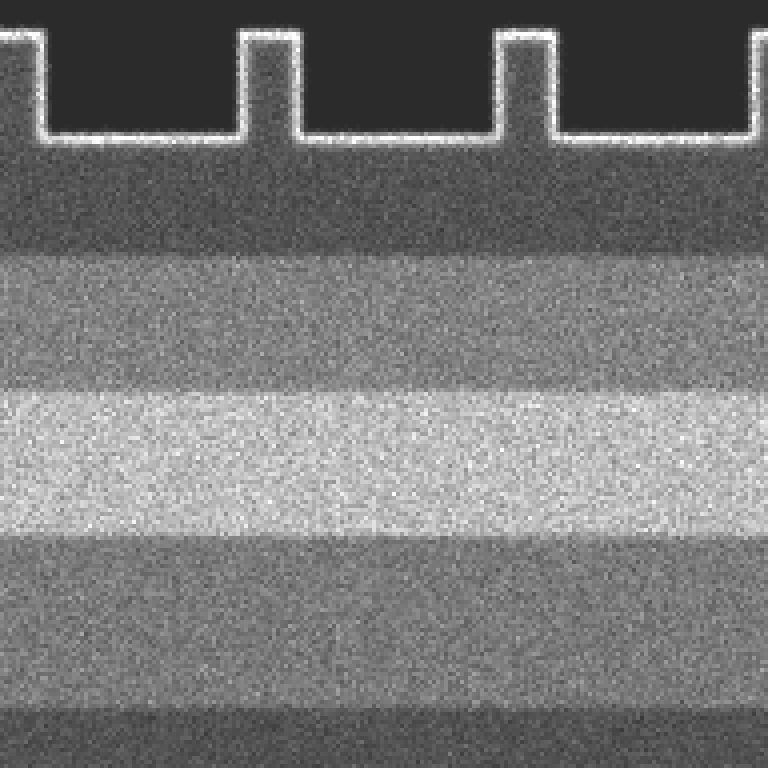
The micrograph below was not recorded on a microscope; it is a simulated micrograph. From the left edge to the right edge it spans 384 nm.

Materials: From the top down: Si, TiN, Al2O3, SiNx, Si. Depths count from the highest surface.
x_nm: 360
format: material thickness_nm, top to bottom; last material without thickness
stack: empty 52, Si 60, TiN 68, Al2O3 72, SiNx 86, Si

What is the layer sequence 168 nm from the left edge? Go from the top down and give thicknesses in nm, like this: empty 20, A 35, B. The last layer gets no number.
empty 52, Si 60, TiN 68, Al2O3 72, SiNx 86, Si